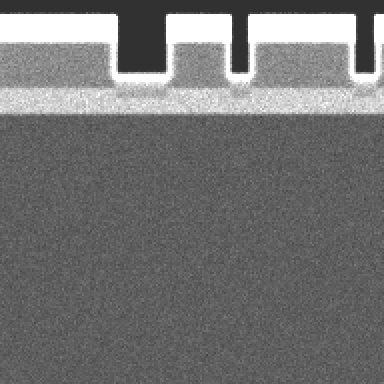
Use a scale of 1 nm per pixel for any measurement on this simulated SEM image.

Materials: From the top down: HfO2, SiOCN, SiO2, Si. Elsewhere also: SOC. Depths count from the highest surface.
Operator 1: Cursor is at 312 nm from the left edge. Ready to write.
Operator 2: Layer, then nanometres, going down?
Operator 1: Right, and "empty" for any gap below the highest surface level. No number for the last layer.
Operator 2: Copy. HfO2 26, SiOCN 46, SiO2 26, Si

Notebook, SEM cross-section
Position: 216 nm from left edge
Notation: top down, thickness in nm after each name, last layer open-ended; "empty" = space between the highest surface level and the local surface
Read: HfO2 26, SiOCN 46, SiO2 26, Si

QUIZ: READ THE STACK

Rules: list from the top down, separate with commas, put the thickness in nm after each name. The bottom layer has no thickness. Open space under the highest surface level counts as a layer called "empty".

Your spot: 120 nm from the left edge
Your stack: empty 58, SOC 24, SiO2 16, Si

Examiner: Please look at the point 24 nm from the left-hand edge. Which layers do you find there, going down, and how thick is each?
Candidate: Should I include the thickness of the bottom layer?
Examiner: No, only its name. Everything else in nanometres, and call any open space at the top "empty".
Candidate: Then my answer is HfO2 26, SiOCN 46, SiO2 26, Si